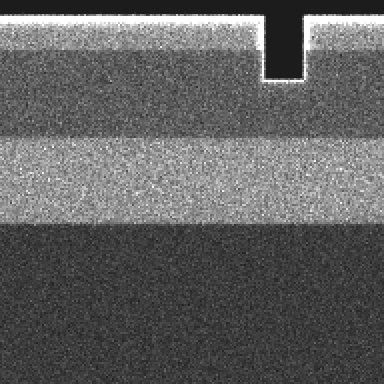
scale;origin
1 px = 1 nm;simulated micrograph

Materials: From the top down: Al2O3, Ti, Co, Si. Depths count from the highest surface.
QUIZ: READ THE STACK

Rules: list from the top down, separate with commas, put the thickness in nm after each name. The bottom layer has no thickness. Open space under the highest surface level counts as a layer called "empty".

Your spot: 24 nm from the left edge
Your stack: Al2O3 34, Ti 88, Co 86, Si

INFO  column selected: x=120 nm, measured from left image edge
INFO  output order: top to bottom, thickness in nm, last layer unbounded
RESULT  Al2O3 34, Ti 88, Co 86, Si